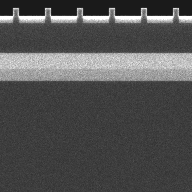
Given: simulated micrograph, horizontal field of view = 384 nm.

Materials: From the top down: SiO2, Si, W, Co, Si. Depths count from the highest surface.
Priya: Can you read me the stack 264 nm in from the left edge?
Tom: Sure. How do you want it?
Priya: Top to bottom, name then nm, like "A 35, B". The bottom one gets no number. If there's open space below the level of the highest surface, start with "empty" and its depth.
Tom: empty 16, SiO2 14, Si 60, W 32, Co 24, Si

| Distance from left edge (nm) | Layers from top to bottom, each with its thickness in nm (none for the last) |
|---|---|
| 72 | empty 16, SiO2 14, Si 60, W 32, Co 24, Si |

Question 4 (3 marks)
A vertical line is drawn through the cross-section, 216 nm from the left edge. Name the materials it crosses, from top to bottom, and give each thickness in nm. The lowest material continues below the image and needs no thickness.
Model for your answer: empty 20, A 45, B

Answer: empty 16, SiO2 14, Si 60, W 32, Co 24, Si